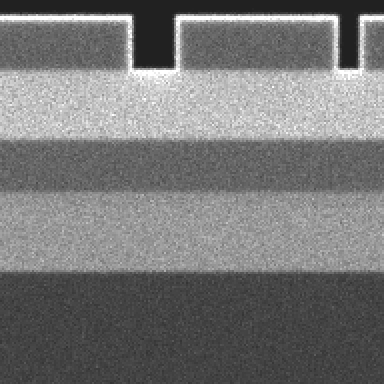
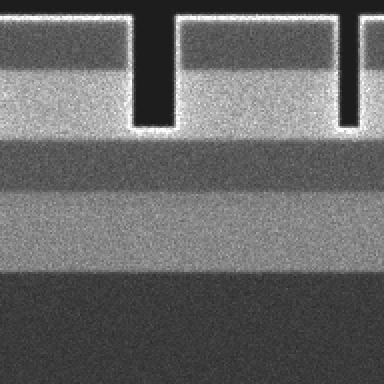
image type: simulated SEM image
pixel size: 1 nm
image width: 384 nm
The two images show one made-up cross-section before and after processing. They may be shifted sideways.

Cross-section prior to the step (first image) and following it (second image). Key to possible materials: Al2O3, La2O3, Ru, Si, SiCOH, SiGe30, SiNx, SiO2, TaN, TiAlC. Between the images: Ru was removed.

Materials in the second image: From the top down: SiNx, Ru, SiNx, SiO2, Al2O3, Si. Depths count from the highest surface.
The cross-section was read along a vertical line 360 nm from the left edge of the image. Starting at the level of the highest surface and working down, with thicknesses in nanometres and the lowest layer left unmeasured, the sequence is SiNx 54, Ru 70, SiNx 52, SiO2 14, Al2O3 66, Si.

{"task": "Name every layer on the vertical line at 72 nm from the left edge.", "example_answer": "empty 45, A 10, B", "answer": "SiNx 54, Ru 70, SiNx 52, SiO2 14, Al2O3 66, Si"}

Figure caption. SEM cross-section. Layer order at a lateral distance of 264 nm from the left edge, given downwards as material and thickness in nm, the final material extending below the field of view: SiNx 54, Ru 70, SiNx 52, SiO2 14, Al2O3 66, Si